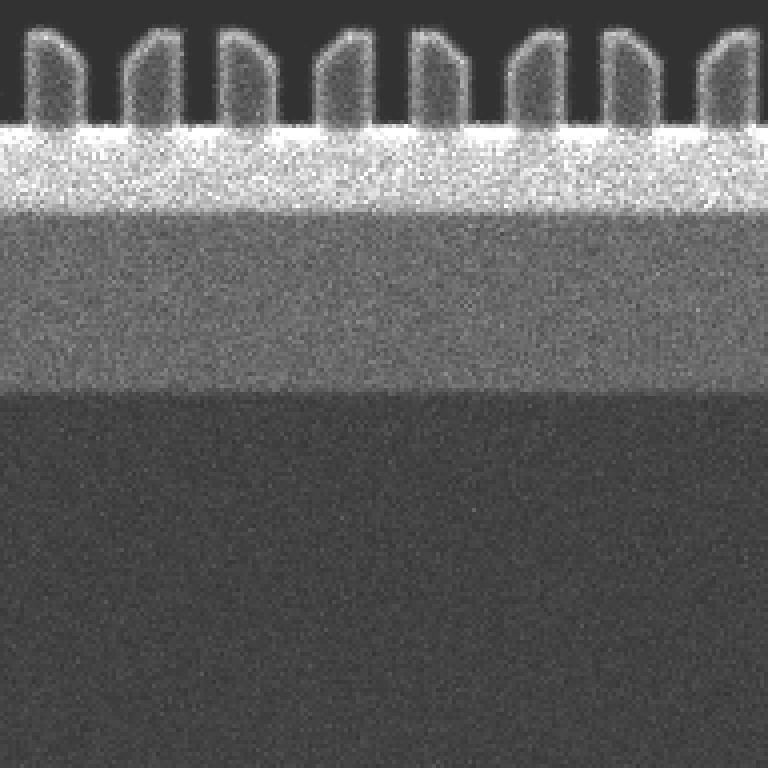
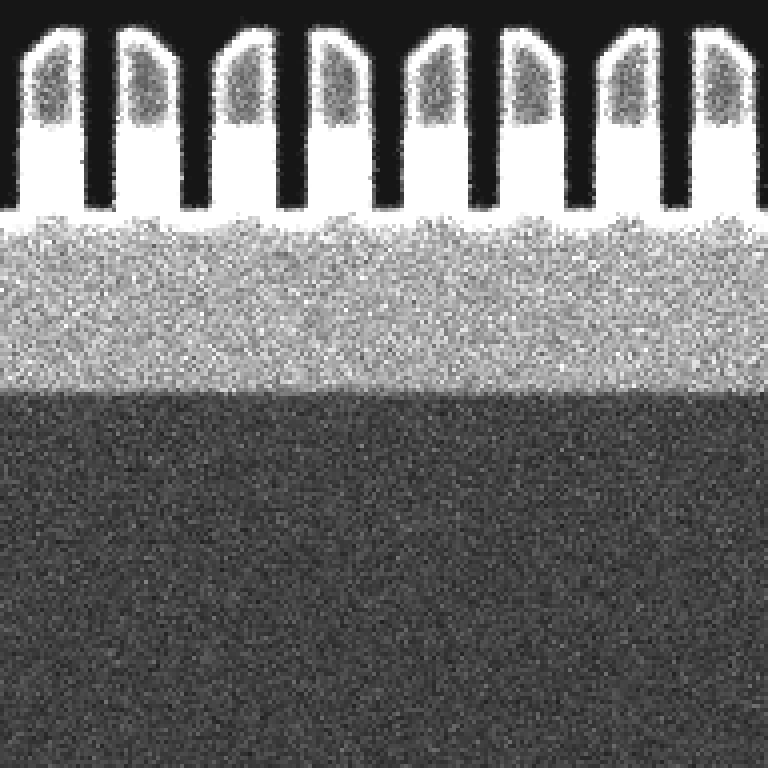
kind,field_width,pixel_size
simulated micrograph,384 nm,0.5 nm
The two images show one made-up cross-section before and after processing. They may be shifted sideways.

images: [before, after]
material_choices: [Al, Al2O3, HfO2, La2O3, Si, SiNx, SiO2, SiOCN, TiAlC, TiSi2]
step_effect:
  removed: HfO2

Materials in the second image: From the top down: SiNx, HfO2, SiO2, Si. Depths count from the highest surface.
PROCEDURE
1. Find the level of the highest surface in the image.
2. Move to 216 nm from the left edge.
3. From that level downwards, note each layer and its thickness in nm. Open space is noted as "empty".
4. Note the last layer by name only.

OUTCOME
empty 2, SiNx 46, HfO2 42, SiO2 90, Si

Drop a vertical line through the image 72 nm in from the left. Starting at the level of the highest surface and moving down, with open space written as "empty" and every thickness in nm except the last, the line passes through SiNx 48, HfO2 42, SiO2 90, Si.